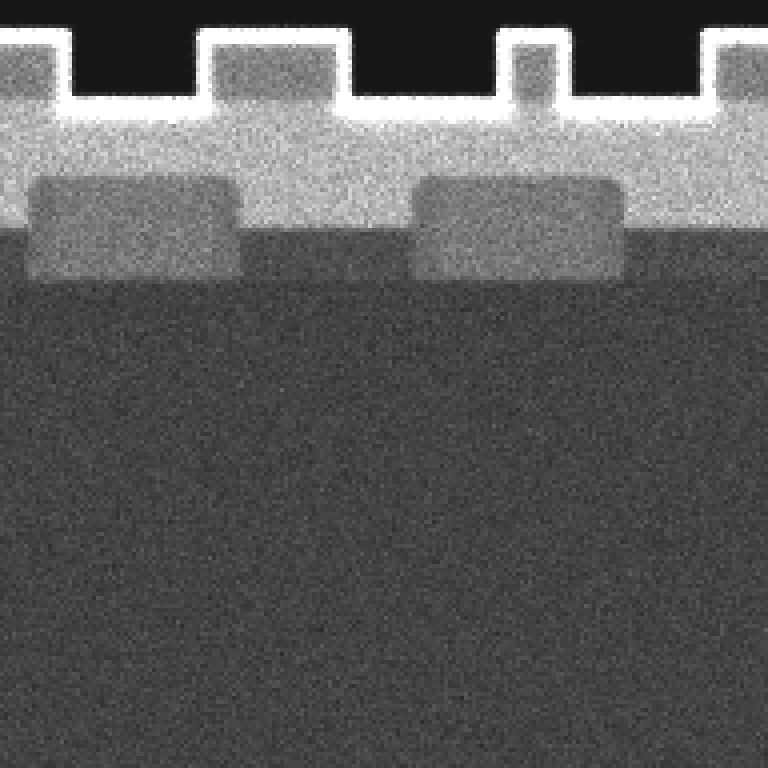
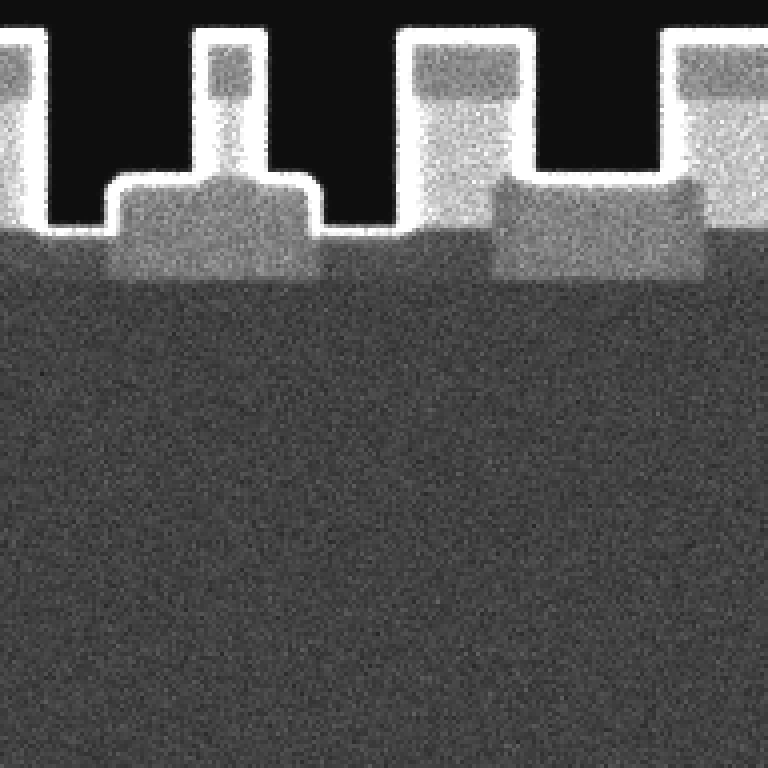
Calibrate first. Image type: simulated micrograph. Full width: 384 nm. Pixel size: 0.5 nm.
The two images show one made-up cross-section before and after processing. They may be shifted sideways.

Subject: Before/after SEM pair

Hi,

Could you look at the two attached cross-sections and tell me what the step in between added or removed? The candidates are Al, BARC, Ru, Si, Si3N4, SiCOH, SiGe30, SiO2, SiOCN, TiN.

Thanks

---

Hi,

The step removed SiO2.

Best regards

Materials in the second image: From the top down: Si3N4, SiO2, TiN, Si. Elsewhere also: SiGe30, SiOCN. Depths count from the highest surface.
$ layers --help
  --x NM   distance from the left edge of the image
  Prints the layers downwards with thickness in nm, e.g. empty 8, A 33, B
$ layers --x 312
empty 72, TiN 52, Si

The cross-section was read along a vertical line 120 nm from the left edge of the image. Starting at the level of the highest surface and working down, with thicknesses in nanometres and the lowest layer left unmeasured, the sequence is Si3N4 34, SiO2 38, TiN 52, Si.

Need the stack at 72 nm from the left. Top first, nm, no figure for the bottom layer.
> empty 72, TiN 52, Si